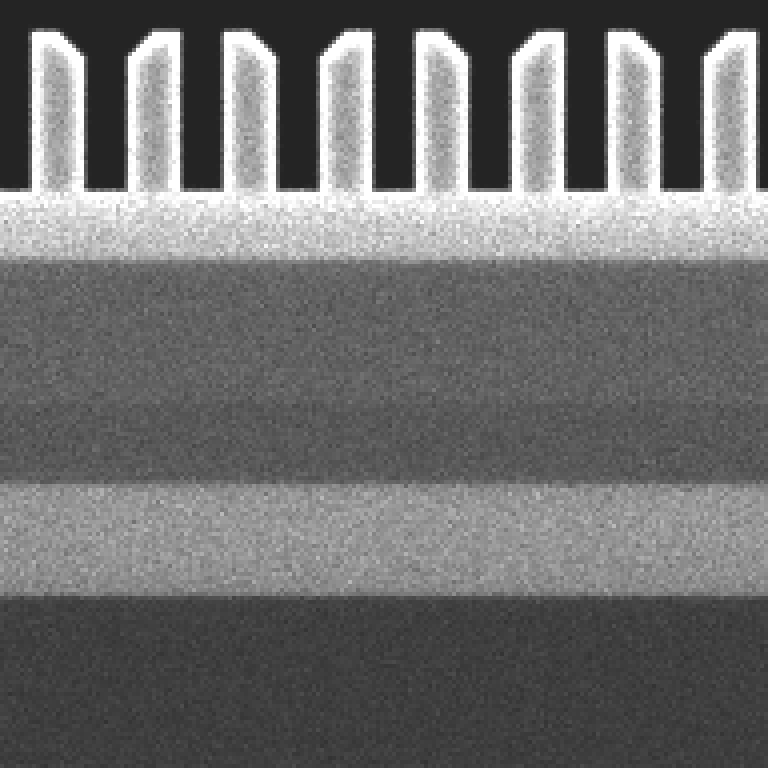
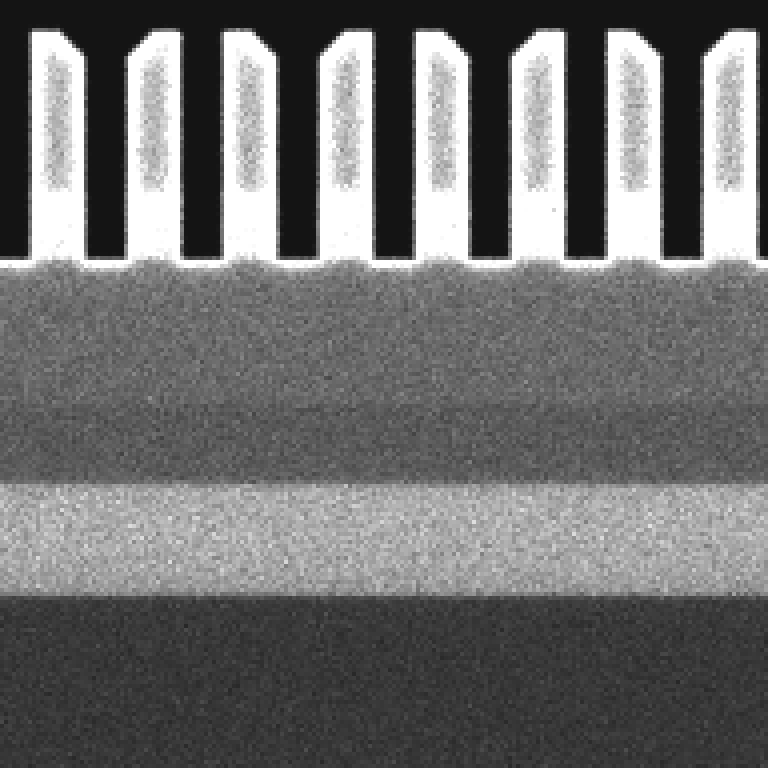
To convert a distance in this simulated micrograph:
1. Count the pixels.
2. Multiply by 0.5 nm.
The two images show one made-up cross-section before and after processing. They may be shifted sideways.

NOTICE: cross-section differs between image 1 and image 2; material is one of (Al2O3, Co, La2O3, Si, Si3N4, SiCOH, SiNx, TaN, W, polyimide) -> removed: W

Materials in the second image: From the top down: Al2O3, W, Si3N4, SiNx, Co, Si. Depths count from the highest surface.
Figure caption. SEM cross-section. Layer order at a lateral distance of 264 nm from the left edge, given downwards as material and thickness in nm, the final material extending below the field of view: empty 4, Al2O3 76, W 34, Si3N4 72, SiNx 40, Co 56, Si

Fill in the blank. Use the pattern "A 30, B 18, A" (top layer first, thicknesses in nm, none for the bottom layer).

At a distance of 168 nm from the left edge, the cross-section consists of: empty 4, Al2O3 76, W 34, Si3N4 72, SiNx 40, Co 56, Si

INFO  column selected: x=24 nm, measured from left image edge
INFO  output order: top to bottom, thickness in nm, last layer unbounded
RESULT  Al2O3 80, W 34, Si3N4 72, SiNx 40, Co 56, Si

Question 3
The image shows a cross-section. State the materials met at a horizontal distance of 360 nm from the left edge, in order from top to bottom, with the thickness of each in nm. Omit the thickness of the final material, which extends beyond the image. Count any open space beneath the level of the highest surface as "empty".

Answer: empty 4, Al2O3 76, W 34, Si3N4 72, SiNx 40, Co 56, Si